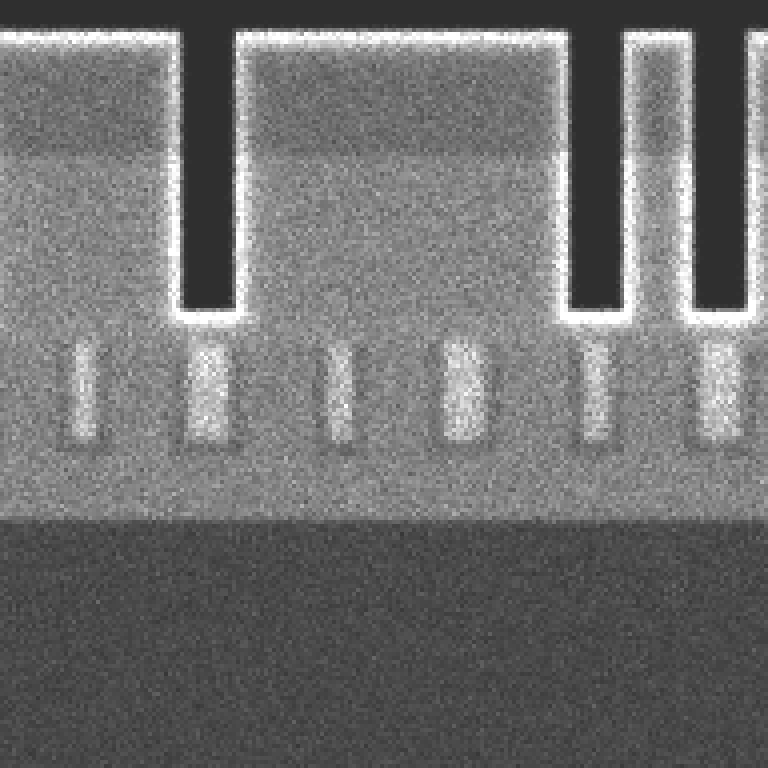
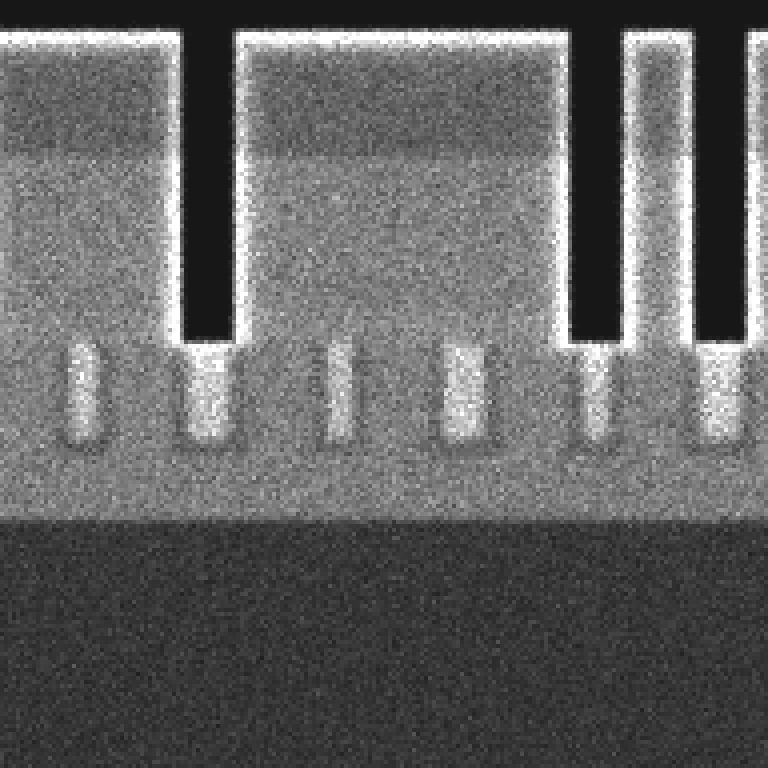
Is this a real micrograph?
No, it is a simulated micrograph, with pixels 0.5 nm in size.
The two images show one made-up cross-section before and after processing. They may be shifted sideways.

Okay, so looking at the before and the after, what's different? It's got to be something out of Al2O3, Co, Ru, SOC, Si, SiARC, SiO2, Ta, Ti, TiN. Al2O3, removed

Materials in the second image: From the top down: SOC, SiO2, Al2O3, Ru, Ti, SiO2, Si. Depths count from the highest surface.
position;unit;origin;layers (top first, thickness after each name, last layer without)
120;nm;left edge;SOC 62, SiO2 78, Al2O3 16, Ti 56, SiO2 32, Si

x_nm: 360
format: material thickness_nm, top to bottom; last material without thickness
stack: empty 156, Ru 48, Ti 8, SiO2 32, Si